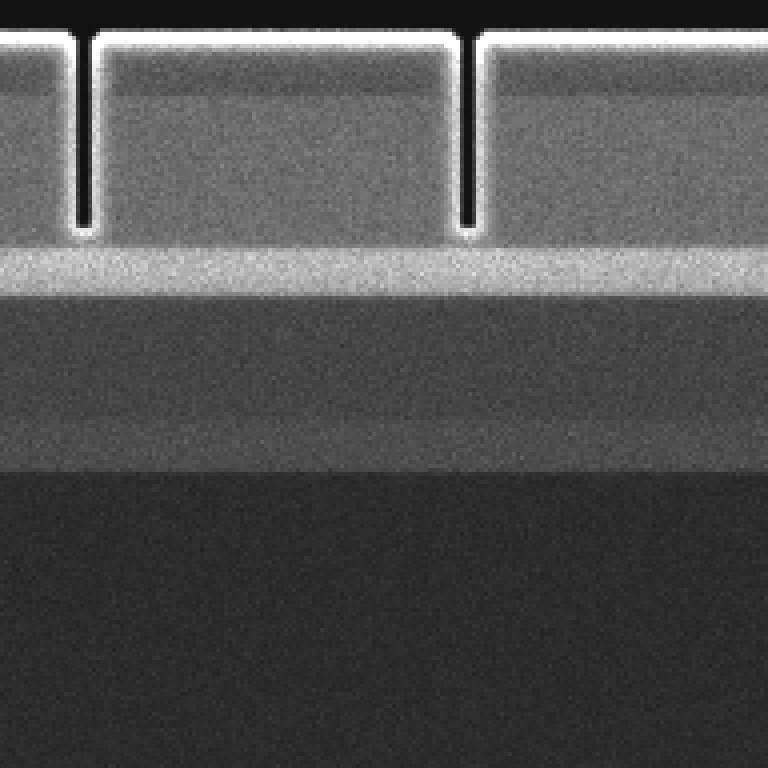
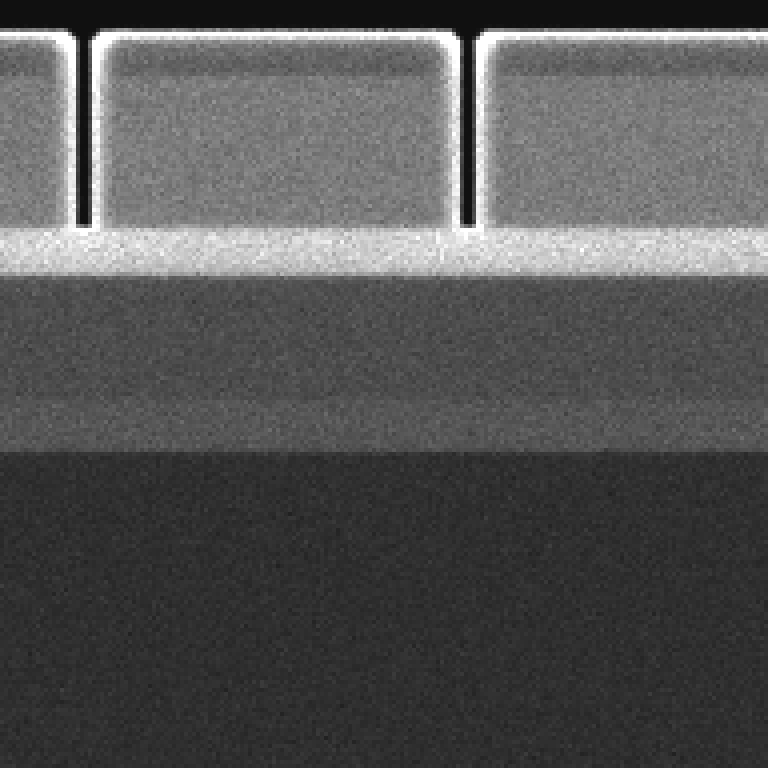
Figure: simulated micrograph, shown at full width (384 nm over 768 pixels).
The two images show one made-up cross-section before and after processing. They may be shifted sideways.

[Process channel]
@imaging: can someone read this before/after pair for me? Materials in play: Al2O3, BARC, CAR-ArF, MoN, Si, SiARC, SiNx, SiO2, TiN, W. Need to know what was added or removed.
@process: Al2O3 removed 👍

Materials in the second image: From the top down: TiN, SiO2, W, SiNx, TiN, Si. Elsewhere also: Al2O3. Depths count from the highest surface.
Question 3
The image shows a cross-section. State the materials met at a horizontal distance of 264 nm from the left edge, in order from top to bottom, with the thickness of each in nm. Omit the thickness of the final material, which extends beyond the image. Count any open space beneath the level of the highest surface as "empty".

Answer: TiN 22, SiO2 76, W 24, SiNx 62, TiN 26, Si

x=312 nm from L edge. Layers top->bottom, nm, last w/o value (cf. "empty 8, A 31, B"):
TiN 22, SiO2 76, W 24, SiNx 62, TiN 26, Si